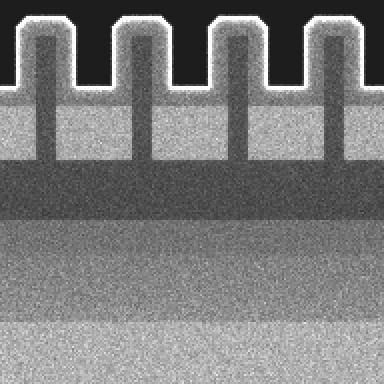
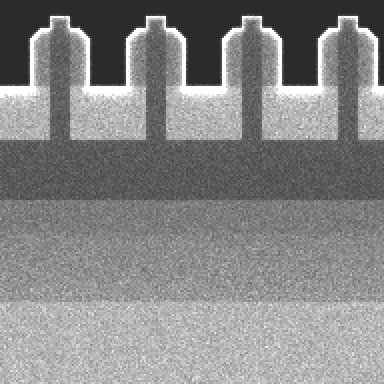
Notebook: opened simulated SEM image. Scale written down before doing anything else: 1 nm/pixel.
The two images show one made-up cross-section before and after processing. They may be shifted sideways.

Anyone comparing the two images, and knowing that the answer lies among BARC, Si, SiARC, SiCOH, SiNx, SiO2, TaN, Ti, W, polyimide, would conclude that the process removed SiNx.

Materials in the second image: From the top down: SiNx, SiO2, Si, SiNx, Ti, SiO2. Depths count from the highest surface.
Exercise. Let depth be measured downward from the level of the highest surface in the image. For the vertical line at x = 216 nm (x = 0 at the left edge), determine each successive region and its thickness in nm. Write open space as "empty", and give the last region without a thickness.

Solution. empty 70, SiO2 54, Si 60, SiNx 34, Ti 68, SiO2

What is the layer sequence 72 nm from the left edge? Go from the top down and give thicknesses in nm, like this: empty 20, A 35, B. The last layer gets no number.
empty 12, SiNx 58, SiO2 54, Si 60, SiNx 34, Ti 68, SiO2